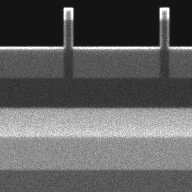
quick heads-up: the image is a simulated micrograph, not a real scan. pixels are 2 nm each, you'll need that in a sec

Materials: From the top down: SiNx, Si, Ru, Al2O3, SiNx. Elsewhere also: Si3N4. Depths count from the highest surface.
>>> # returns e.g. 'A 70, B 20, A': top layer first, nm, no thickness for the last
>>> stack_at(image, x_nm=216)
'empty 78, SiNx 62, Si 60, Ru 58, Al2O3 66, SiNx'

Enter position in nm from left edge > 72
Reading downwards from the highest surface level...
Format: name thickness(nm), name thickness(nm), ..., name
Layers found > empty 78, SiNx 62, Si 60, Ru 58, Al2O3 66, SiNx